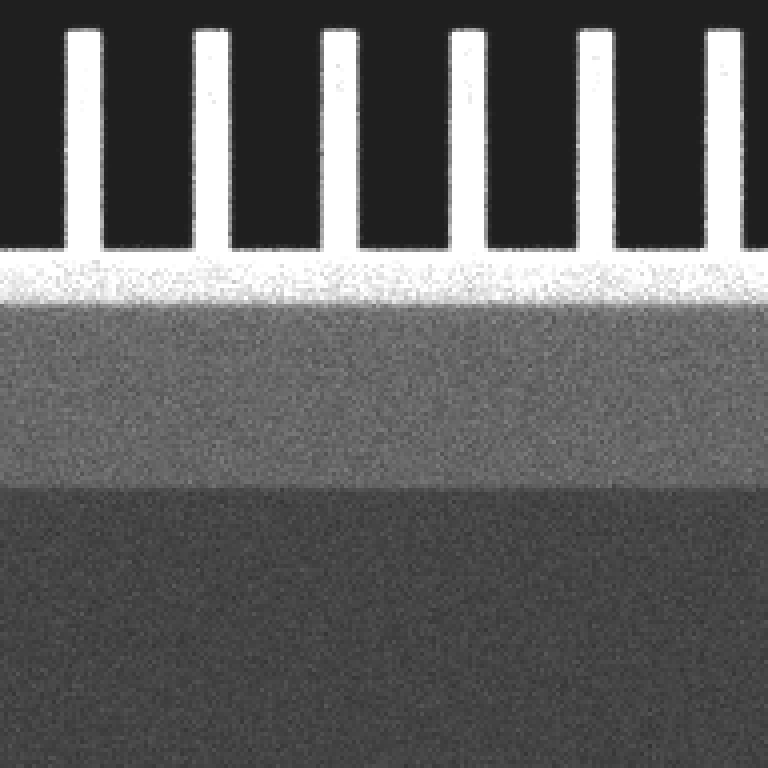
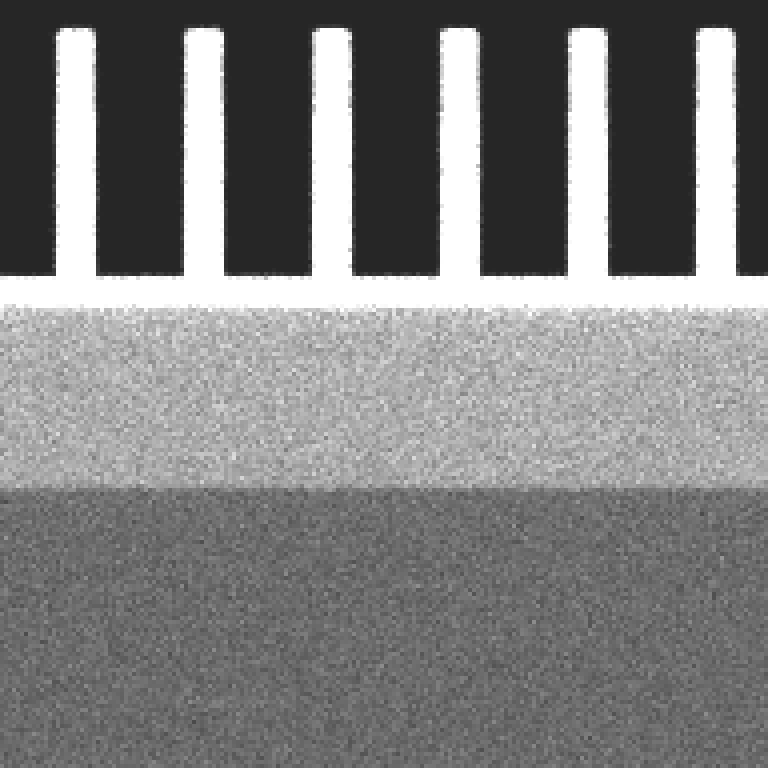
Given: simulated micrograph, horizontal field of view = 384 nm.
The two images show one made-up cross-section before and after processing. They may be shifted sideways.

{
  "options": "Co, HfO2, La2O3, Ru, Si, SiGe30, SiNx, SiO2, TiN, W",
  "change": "removed",
  "material": "Co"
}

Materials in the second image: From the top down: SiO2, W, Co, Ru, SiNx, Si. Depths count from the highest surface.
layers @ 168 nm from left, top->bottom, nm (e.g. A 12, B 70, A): SiO2 40, W 70, Co 14, Ru 12, SiNx 92, Si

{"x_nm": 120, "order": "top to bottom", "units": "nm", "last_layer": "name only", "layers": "empty 124, Ru 12, SiNx 92, Si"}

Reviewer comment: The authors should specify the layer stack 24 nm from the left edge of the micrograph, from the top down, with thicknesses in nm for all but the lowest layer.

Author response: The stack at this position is empty 124, Ru 12, SiNx 92, Si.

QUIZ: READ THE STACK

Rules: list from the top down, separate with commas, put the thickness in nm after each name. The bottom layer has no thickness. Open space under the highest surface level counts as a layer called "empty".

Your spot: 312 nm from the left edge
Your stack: empty 124, Ru 12, SiNx 92, Si